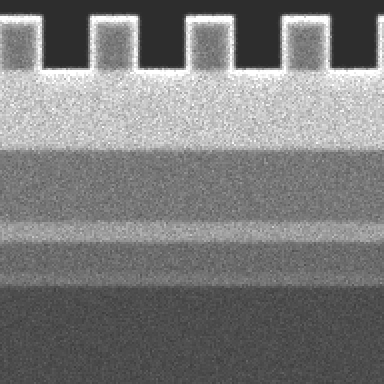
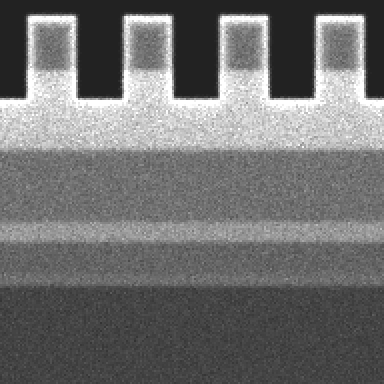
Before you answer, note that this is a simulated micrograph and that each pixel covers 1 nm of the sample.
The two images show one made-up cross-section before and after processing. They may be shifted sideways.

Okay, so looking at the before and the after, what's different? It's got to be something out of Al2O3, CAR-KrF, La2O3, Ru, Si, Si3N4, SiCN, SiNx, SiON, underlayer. Ru, removed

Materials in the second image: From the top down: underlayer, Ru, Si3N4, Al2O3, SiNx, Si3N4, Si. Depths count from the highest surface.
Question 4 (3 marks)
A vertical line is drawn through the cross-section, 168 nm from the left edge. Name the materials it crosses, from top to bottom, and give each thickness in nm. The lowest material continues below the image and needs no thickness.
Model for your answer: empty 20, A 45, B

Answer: underlayer 54, Ru 80, Si3N4 72, Al2O3 20, SiNx 32, Si3N4 12, Si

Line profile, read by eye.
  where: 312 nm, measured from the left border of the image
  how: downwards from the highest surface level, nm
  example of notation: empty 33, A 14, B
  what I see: empty 84, Ru 50, Si3N4 72, Al2O3 20, SiNx 32, Si3N4 12, Si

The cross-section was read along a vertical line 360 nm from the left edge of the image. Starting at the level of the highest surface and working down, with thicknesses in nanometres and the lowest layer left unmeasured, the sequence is underlayer 54, Ru 80, Si3N4 72, Al2O3 20, SiNx 32, Si3N4 12, Si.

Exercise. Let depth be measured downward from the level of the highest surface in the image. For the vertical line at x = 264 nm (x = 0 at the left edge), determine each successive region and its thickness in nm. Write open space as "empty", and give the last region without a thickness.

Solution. underlayer 54, Ru 80, Si3N4 72, Al2O3 20, SiNx 32, Si3N4 12, Si